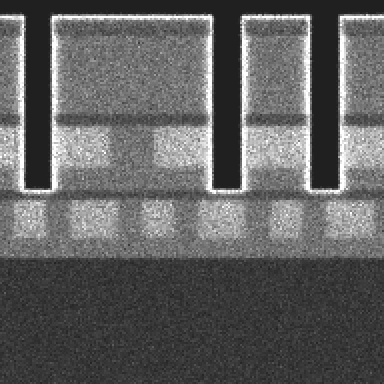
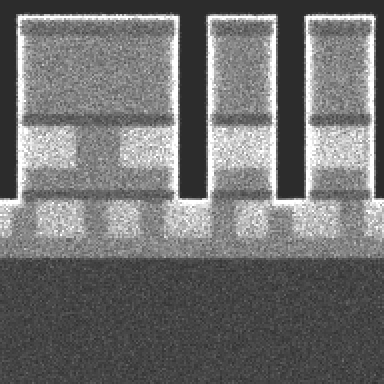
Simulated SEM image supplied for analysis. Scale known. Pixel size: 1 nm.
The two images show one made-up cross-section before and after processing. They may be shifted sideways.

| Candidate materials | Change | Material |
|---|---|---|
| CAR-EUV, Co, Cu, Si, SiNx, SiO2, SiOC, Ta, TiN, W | removed | SiNx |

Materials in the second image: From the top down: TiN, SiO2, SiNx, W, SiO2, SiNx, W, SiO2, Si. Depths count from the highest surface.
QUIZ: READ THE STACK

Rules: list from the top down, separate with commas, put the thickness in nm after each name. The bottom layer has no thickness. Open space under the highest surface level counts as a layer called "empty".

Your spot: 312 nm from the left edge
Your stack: TiN 20, SiO2 78, SiNx 12, W 42, SiO2 22, SiNx 10, W 38, SiO2 20, Si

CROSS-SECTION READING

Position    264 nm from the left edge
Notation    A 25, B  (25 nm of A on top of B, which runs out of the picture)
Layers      TiN 20, SiO2 78, SiNx 12, W 42, SiO2 22, SiNx 10, W 38, SiO2 20, Si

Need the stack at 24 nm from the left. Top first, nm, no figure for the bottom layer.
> TiN 20, SiO2 78, SiNx 12, W 42, SiO2 22, SiNx 10, SiO2 58, Si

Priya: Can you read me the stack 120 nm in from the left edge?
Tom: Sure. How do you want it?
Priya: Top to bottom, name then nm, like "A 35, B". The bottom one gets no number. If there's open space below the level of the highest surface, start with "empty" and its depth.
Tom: TiN 20, SiO2 78, SiNx 12, W 42, SiO2 22, SiNx 10, W 38, SiO2 20, Si